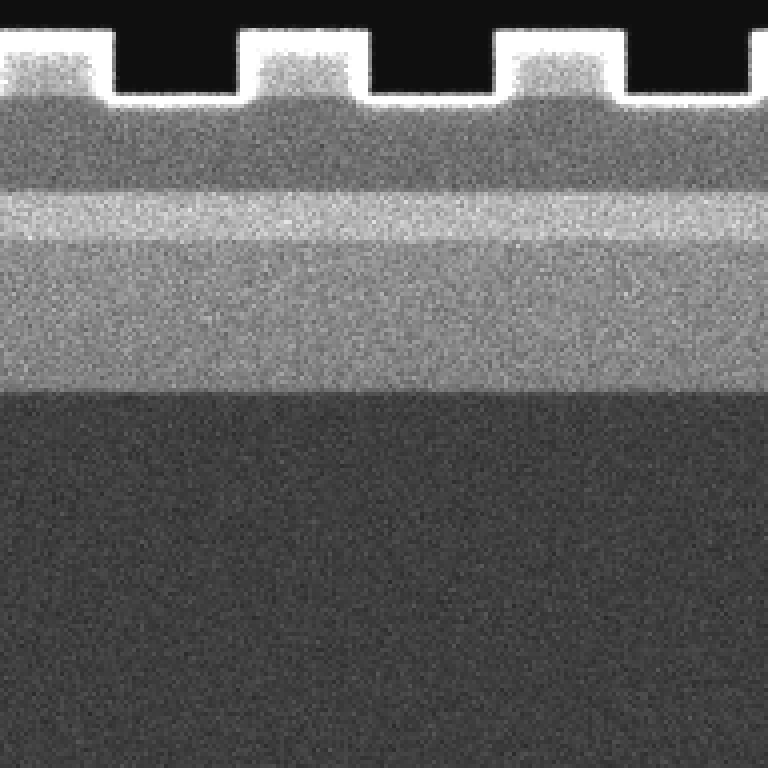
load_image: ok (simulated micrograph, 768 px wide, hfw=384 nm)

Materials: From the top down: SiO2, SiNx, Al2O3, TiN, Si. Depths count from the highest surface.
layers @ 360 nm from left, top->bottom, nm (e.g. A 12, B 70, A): empty 32, SiNx 48, Al2O3 24, TiN 76, Si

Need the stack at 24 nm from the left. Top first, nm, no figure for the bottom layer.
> SiO2 32, SiNx 48, Al2O3 24, TiN 76, Si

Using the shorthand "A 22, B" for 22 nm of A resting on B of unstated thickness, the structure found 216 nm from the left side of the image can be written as empty 32, SiNx 48, Al2O3 24, TiN 76, Si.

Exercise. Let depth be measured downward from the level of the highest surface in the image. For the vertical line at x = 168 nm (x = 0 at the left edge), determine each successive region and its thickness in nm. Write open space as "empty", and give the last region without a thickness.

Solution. SiO2 32, SiNx 48, Al2O3 24, TiN 76, Si